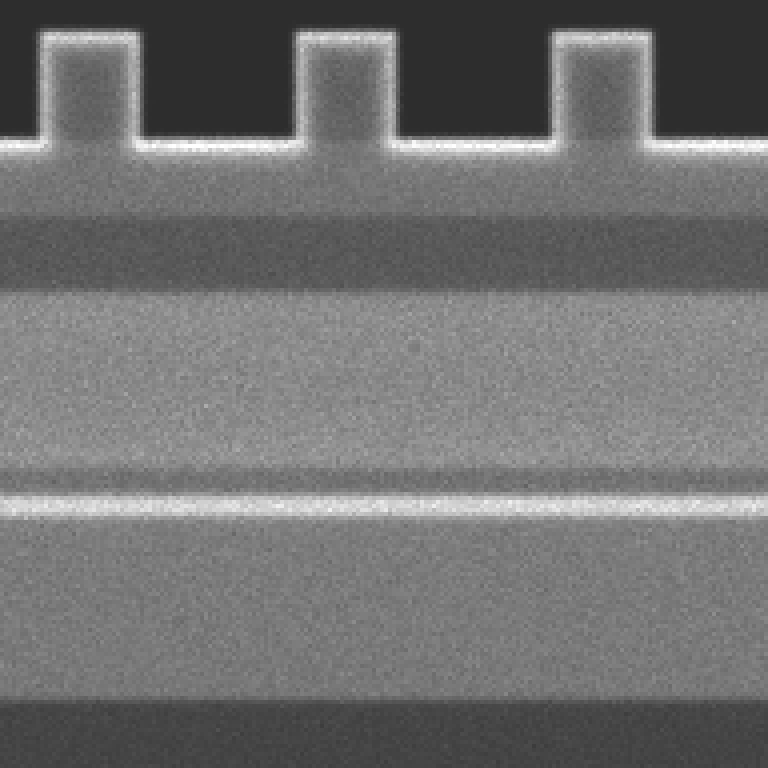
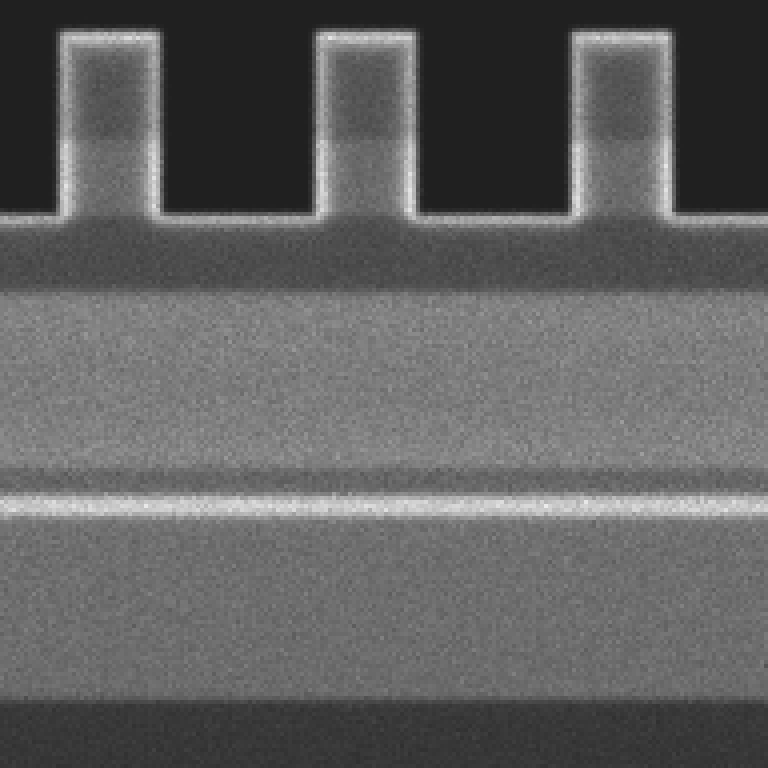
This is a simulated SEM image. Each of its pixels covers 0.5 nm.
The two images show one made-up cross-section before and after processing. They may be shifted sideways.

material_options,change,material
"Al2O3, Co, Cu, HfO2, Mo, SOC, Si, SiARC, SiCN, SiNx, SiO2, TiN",removed,SiO2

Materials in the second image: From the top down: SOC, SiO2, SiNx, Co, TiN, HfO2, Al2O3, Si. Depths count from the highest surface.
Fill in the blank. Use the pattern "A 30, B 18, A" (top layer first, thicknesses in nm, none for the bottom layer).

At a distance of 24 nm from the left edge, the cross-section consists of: empty 92, SiNx 38, Co 88, TiN 14, HfO2 10, Al2O3 92, Si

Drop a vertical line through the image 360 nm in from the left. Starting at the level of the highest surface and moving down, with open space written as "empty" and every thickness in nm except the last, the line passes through empty 92, SiNx 38, Co 88, TiN 14, HfO2 10, Al2O3 92, Si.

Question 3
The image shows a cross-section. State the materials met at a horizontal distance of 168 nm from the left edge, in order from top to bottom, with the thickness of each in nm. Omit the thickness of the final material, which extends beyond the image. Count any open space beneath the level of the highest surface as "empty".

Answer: SOC 54, SiO2 38, SiNx 38, Co 88, TiN 14, HfO2 10, Al2O3 92, Si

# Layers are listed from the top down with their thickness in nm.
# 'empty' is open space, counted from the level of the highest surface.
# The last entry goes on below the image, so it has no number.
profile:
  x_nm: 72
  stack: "SOC 54, SiO2 38, SiNx 38, Co 88, TiN 14, HfO2 10, Al2O3 92, Si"